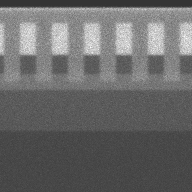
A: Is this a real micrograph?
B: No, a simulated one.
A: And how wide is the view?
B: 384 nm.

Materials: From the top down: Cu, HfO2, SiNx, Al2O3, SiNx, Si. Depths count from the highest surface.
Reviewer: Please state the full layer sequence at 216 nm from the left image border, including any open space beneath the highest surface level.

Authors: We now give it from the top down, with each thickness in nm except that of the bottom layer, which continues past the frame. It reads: Cu 146, Al2O3 18, SiNx 82, Si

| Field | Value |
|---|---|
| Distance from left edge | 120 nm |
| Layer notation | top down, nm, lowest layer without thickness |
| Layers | Cu 30, HfO2 64, SiNx 38, Al2O3 32, SiNx 82, Si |